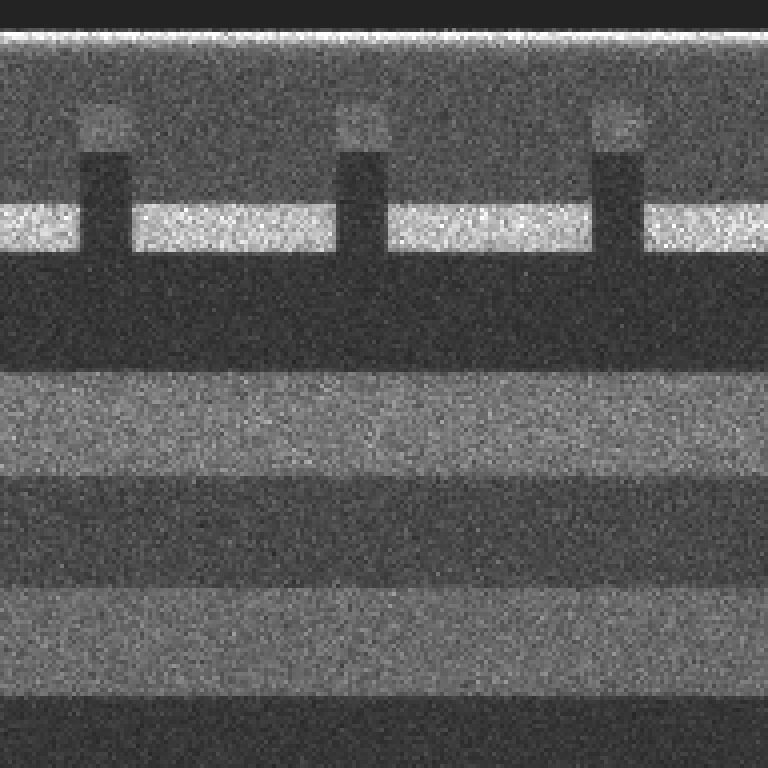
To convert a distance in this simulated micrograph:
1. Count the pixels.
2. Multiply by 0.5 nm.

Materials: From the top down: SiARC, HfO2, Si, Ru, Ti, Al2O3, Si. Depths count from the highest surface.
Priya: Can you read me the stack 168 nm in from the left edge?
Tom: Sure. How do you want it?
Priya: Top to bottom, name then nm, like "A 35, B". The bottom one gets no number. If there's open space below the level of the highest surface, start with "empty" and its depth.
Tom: SiARC 36, Al2O3 24, Si 110, Ru 52, Ti 56, Al2O3 54, Si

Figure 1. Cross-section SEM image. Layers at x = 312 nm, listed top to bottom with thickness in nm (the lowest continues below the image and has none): SiARC 36, Al2O3 24, Si 110, Ru 52, Ti 56, Al2O3 54, Si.